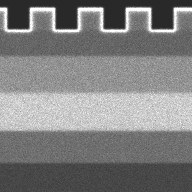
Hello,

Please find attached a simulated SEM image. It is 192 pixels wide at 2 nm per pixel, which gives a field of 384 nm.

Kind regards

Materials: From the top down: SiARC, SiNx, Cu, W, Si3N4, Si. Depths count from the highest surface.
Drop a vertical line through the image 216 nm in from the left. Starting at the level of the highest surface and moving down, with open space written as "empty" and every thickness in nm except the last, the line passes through empty 44, SiNx 52, Cu 74, W 76, Si3N4 64, Si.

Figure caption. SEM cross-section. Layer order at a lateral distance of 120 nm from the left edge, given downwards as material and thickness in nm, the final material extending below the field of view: empty 44, SiNx 52, Cu 74, W 76, Si3N4 64, Si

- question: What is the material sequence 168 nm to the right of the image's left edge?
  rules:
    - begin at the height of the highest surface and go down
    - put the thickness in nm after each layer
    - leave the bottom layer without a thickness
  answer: SiARC 44, SiNx 52, Cu 74, W 76, Si3N4 64, Si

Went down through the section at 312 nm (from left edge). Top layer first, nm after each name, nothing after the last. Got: empty 44, SiNx 52, Cu 74, W 76, Si3N4 64, Si